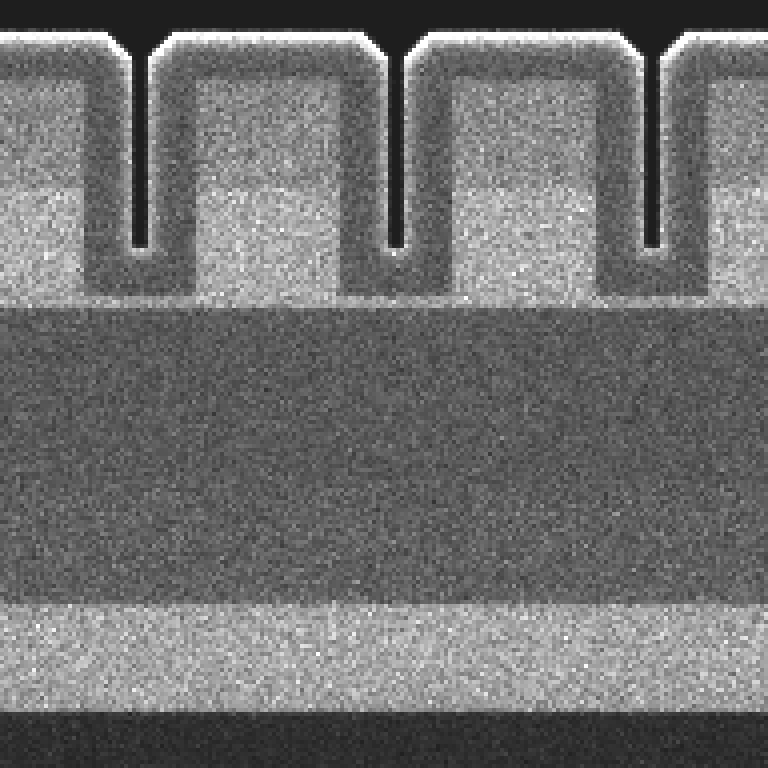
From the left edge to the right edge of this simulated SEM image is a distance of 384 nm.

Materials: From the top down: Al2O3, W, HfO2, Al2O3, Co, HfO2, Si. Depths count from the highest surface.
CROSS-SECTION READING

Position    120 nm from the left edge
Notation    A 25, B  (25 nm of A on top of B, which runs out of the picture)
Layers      Al2O3 24, W 54, HfO2 60, Al2O3 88, Co 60, HfO2 54, Si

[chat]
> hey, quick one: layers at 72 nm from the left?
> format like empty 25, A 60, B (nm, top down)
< empty 108, Al2O3 24, HfO2 6, Al2O3 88, Co 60, HfO2 54, Si